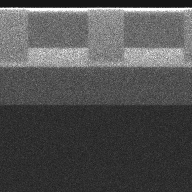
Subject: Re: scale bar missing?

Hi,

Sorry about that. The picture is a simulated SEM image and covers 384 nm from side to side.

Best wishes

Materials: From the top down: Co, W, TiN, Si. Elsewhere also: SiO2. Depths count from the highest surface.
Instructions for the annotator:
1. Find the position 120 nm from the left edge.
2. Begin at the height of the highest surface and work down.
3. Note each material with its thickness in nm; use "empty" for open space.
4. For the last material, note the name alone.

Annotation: SiO2 80, W 38, TiN 76, Si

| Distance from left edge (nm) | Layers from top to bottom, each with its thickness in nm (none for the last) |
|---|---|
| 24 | Co 108, W 10, TiN 76, Si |